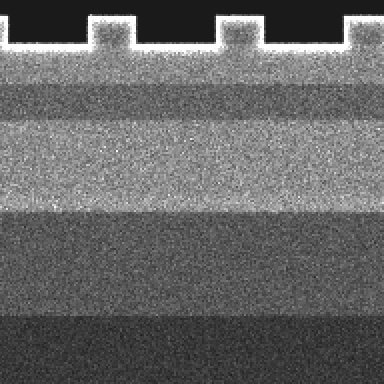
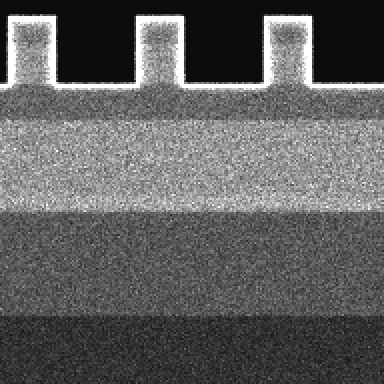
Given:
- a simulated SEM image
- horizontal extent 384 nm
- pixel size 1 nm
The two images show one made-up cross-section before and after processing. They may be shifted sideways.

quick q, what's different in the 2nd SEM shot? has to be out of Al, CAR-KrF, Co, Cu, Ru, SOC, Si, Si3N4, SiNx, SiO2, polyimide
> SiO2 removed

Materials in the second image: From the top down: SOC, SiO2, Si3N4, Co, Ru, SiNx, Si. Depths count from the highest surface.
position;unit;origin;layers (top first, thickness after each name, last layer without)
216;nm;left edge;empty 68, Si3N4 36, Co 76, Ru 16, SiNx 104, Si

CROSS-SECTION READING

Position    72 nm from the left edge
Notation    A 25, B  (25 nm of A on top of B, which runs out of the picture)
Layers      empty 68, Si3N4 36, Co 76, Ru 16, SiNx 104, Si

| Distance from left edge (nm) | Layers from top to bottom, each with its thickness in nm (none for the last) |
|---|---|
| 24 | SOC 28, SiO2 40, Si3N4 36, Co 76, Ru 16, SiNx 104, Si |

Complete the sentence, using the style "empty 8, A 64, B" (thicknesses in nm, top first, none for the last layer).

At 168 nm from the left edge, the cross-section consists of SOC 28, SiO2 40, Si3N4 36, Co 76, Ru 16, SiNx 104, Si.